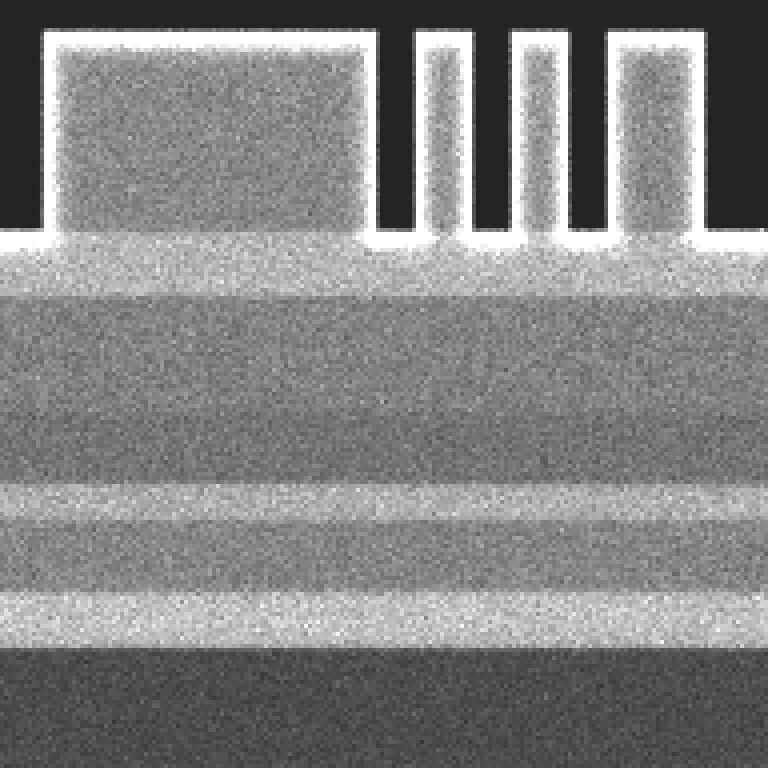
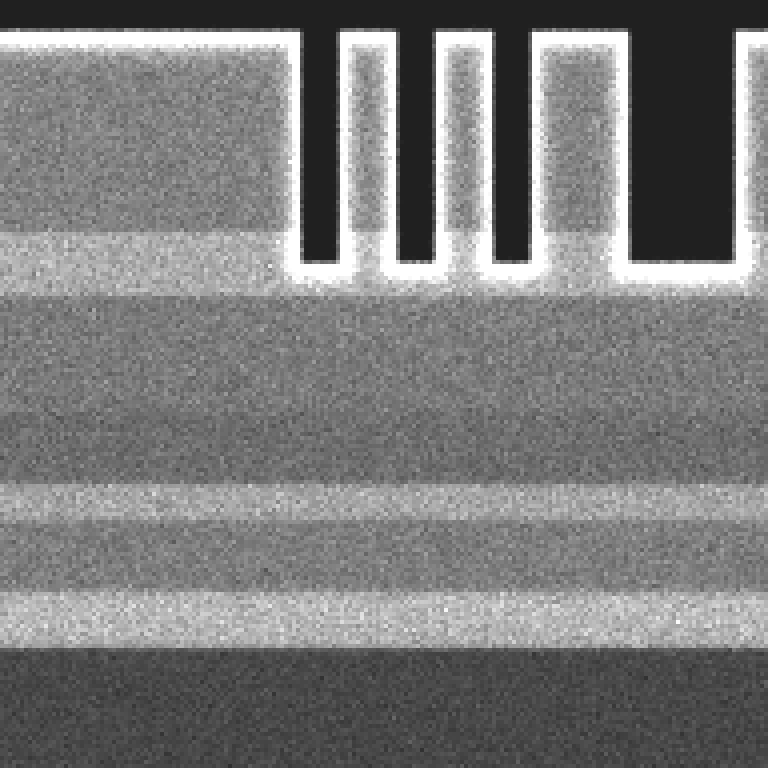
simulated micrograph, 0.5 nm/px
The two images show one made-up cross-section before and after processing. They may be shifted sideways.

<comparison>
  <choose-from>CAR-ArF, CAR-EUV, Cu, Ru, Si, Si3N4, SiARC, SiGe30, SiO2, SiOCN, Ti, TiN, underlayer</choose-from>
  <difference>SiO2 removed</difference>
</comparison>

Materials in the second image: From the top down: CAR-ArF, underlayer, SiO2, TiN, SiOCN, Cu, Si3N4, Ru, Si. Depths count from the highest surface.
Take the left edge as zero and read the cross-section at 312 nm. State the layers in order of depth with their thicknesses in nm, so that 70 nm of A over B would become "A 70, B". CAR-ArF 68, underlayer 32, SiO2 32, TiN 58, SiOCN 36, Cu 18, Si3N4 36, Ru 28, Si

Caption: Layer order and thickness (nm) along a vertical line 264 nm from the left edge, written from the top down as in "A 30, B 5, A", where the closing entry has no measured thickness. empty 116, SiO2 16, TiN 58, SiOCN 36, Cu 18, Si3N4 36, Ru 28, Si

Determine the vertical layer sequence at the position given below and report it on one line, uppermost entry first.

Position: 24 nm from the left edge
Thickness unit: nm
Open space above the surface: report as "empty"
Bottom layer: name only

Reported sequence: CAR-ArF 68, underlayer 32, SiO2 32, TiN 58, SiOCN 36, Cu 18, Si3N4 36, Ru 28, Si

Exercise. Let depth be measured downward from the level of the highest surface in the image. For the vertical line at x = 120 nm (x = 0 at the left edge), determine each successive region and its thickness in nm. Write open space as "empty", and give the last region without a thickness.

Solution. CAR-ArF 68, underlayer 32, SiO2 32, TiN 58, SiOCN 36, Cu 18, Si3N4 36, Ru 28, Si